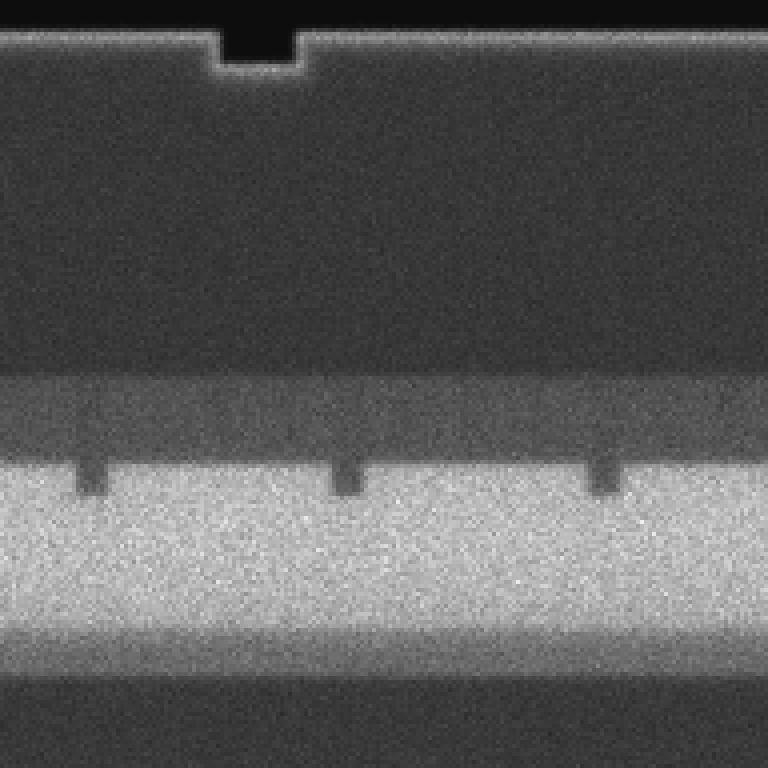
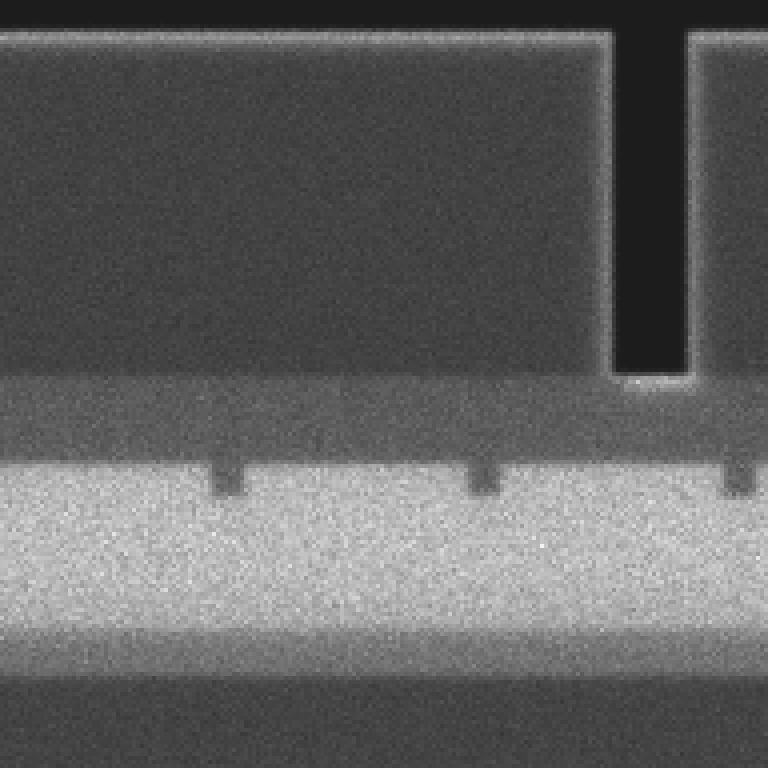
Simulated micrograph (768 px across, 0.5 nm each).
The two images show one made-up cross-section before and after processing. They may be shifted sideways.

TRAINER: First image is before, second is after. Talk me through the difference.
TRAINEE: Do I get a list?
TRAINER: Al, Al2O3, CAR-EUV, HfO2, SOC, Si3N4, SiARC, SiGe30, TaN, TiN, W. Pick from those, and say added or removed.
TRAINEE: removed: SOC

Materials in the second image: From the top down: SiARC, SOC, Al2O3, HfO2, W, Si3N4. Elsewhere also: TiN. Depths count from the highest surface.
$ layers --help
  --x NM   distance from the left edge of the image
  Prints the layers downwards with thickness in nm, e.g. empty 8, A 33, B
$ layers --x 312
empty 172, TiN 44, HfO2 82, W 24, Si3N4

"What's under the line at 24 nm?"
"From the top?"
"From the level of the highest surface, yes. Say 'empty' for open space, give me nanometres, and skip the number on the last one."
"SiARC 16, SOC 156, Al2O3 44, HfO2 82, W 24, Si3N4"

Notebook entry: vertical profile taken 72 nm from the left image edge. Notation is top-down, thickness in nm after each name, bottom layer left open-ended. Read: SiARC 16, SOC 156, Al2O3 44, HfO2 82, W 24, Si3N4